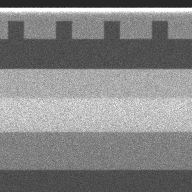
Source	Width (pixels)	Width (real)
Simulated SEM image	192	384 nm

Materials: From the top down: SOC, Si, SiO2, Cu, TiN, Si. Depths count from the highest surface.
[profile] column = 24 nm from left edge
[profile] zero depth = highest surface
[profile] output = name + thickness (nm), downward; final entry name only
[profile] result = SOC 26, Si 96, SiO2 58, Cu 68, TiN 76, Si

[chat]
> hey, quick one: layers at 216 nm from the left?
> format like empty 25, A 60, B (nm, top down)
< SOC 26, Si 96, SiO2 58, Cu 68, TiN 76, Si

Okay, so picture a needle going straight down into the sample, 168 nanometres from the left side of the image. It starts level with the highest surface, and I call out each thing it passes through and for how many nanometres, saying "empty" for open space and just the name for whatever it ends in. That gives SOC 62, Si 60, SiO2 58, Cu 68, TiN 76, Si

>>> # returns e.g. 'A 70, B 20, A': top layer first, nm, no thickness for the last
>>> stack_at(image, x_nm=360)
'SOC 62, Si 60, SiO2 58, Cu 68, TiN 76, Si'